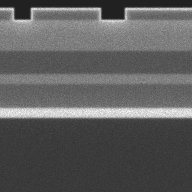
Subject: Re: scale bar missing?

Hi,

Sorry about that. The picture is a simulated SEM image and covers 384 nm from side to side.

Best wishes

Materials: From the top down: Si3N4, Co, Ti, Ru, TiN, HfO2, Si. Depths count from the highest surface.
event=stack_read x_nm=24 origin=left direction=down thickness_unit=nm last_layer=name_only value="Si3N4 24, Co 62, Ti 46, Ru 20, TiN 48, HfO2 20, Si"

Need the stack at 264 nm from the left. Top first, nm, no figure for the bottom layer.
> Si3N4 24, Co 62, Ti 46, Ru 20, TiN 48, HfO2 20, Si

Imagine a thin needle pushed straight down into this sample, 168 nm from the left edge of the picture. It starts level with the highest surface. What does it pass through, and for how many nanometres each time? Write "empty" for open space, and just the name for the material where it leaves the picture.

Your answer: Si3N4 24, Co 62, Ti 46, Ru 20, TiN 48, HfO2 20, Si